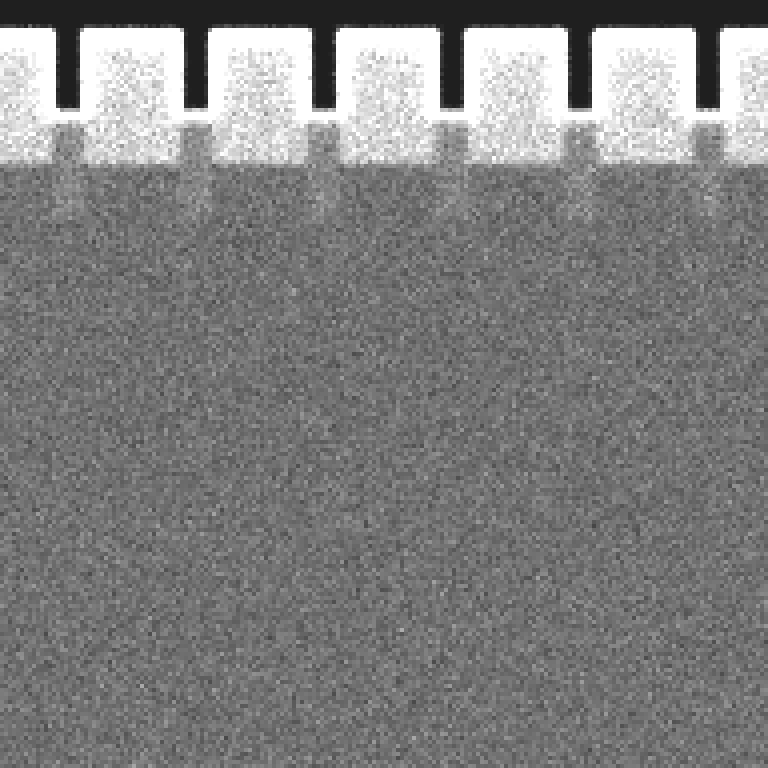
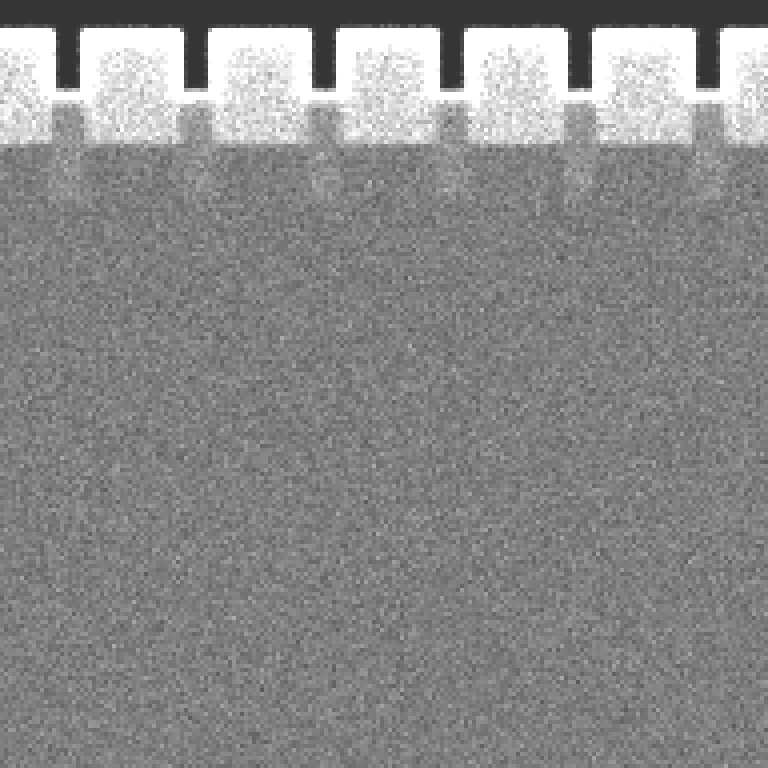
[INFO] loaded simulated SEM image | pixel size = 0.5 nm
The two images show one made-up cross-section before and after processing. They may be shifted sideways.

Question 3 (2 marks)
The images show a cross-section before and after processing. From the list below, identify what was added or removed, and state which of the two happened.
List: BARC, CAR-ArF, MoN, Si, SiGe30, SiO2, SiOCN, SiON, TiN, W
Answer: TiN was removed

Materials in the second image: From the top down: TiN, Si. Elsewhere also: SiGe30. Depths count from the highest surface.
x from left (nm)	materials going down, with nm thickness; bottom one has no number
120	TiN 56, Si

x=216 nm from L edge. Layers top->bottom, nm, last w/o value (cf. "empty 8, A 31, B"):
TiN 56, Si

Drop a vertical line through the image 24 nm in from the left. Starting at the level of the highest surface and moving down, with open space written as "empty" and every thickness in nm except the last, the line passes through TiN 56, Si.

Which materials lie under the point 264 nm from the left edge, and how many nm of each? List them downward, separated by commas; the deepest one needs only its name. TiN 56, Si